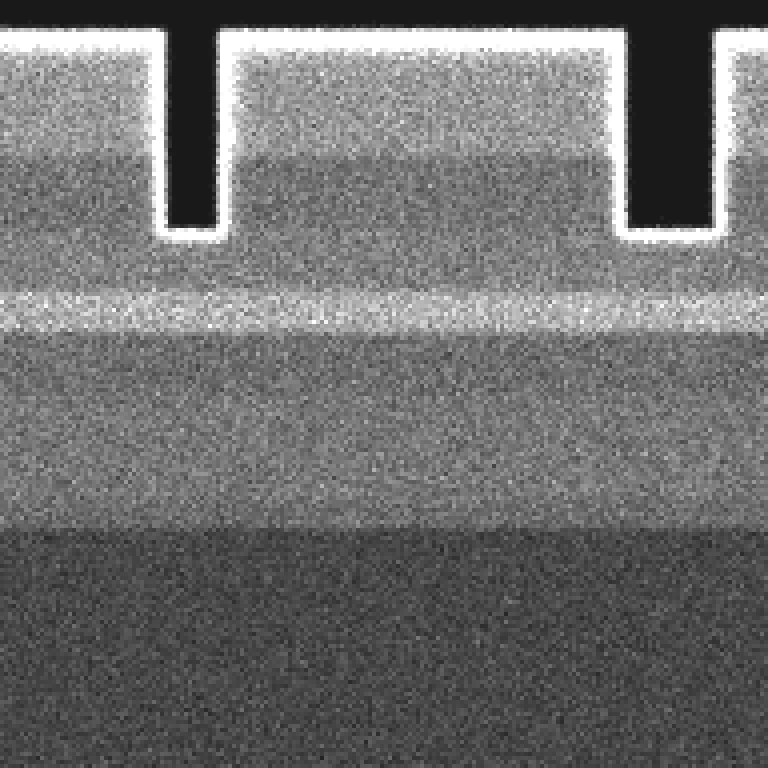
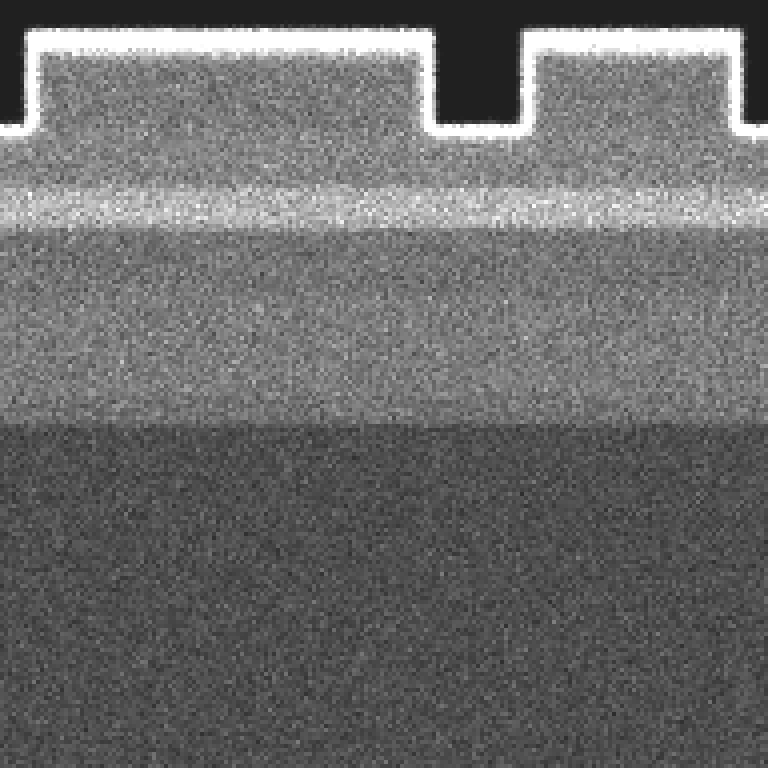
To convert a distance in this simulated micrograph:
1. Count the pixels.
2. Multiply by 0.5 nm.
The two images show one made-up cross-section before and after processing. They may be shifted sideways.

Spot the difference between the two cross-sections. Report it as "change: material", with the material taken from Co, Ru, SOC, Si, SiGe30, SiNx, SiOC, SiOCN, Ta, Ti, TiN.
removed: SOC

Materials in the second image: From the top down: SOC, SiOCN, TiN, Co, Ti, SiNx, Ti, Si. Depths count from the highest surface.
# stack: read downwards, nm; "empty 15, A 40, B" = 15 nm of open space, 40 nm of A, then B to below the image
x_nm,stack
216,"empty 48, TiN 30, Co 20, Ti 32, SiNx 52, Ti 14, Si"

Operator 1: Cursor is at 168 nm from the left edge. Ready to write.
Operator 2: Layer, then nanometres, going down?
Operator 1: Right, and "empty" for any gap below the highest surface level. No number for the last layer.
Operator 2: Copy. SOC 10, SiOCN 38, TiN 30, Co 20, Ti 32, SiNx 52, Ti 14, Si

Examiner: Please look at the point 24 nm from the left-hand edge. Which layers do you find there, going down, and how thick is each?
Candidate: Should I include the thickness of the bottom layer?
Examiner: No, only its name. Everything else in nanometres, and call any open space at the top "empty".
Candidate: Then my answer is SOC 10, SiOCN 38, TiN 30, Co 20, Ti 32, SiNx 52, Ti 14, Si